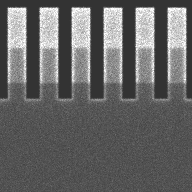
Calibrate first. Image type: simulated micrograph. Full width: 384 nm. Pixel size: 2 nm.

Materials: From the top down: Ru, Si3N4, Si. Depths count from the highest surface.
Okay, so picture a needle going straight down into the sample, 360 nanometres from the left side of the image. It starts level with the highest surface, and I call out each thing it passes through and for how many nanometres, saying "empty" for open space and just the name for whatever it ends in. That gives Ru 80, Si3N4 70, Si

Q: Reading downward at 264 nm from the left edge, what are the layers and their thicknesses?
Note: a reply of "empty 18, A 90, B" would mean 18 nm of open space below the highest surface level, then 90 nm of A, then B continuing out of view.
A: empty 182, Si